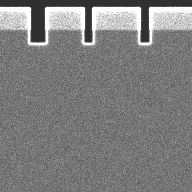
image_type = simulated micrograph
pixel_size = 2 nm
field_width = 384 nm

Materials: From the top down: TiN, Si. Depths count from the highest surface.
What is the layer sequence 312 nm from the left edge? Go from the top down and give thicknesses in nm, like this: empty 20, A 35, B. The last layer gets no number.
TiN 44, Si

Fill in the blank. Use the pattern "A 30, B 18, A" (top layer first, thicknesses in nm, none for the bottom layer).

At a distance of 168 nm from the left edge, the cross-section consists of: empty 70, Si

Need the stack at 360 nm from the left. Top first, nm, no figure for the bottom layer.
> TiN 44, Si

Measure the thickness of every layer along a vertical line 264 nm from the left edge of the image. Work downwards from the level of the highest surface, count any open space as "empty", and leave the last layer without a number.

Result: TiN 44, Si